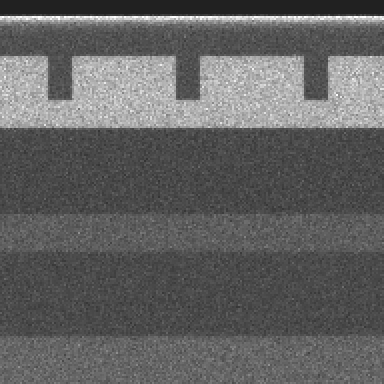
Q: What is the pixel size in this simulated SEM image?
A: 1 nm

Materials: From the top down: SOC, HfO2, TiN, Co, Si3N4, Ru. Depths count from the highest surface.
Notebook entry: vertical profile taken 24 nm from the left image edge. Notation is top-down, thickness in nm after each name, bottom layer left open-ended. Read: SOC 40, HfO2 72, TiN 86, Co 38, Si3N4 84, Ru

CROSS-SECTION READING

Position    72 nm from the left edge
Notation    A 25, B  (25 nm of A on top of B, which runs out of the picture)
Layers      SOC 40, HfO2 72, TiN 86, Co 38, Si3N4 84, Ru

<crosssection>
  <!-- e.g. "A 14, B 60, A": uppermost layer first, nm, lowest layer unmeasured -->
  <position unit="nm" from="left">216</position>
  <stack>SOC 40, HfO2 72, TiN 86, Co 38, Si3N4 84, Ru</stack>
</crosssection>